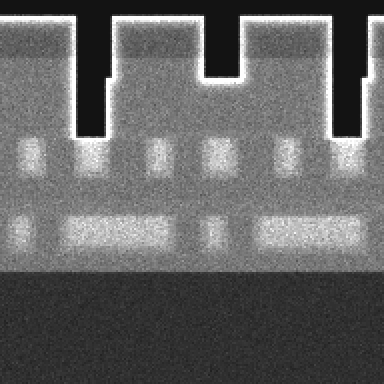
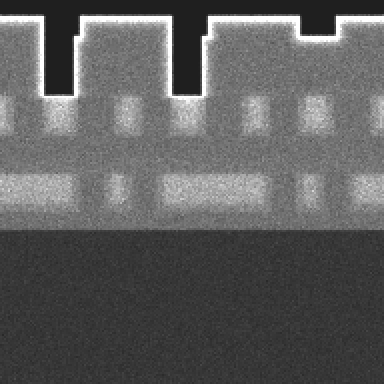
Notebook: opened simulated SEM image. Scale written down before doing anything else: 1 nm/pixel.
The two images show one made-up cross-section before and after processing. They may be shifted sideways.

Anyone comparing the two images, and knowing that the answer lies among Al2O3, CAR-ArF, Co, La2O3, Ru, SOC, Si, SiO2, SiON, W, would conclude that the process removed SOC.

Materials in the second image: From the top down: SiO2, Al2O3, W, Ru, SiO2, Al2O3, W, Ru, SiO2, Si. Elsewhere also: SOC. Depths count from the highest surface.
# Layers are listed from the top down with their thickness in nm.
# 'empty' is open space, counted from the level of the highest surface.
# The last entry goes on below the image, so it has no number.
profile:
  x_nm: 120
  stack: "SiO2 72, Al2O3 8, Ru 40, SiO2 22, Al2O3 16, W 30, Ru 8, SiO2 18, Si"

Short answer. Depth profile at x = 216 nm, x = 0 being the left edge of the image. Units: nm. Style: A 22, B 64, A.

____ SiO2 72, Al2O3 8, SiO2 62, Al2O3 16, W 30, Ru 8, SiO2 18, Si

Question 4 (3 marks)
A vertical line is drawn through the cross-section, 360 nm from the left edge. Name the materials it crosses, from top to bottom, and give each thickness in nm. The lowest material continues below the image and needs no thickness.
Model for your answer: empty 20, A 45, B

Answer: SiO2 72, Al2O3 8, SiO2 62, Al2O3 16, W 30, Ru 8, SiO2 18, Si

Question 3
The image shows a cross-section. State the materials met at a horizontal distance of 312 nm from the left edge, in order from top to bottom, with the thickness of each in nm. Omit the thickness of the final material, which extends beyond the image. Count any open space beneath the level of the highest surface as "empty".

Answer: empty 20, SiO2 52, Al2O3 8, W 32, Ru 8, SiO2 22, Al2O3 16, W 30, Ru 8, SiO2 18, Si